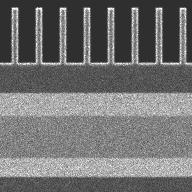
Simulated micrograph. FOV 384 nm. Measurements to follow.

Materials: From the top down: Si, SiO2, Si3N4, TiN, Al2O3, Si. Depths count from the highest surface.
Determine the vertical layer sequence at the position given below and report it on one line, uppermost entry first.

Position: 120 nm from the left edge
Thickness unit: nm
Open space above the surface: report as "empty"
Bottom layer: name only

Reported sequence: Si 170, SiO2 46, Si3N4 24, TiN 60, Al2O3 38, Si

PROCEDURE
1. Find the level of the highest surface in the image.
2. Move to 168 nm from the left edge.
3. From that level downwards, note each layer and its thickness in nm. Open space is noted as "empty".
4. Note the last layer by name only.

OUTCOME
Si 170, SiO2 46, Si3N4 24, TiN 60, Al2O3 38, Si